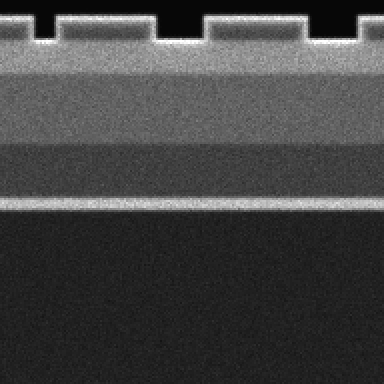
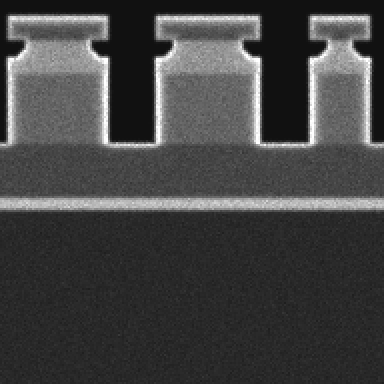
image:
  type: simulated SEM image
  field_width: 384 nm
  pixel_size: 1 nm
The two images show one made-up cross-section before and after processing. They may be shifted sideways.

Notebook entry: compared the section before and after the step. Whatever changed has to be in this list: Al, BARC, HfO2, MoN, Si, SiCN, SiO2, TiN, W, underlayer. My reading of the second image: SiO2 and W removed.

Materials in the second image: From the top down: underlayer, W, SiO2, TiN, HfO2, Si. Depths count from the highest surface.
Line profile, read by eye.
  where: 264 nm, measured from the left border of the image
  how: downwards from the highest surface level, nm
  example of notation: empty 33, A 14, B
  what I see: empty 128, TiN 54, HfO2 12, Si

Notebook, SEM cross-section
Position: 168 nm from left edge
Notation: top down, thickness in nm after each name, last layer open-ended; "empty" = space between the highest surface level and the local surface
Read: underlayer 24, empty 14, W 20, SiO2 70, TiN 54, HfO2 12, Si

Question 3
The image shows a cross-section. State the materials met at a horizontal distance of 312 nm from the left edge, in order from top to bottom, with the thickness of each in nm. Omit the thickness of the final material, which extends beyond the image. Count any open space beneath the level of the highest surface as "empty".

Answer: underlayer 24, empty 18, W 16, SiO2 70, TiN 54, HfO2 12, Si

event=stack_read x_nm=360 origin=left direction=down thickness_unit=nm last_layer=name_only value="underlayer 24, empty 18, W 16, SiO2 70, TiN 54, HfO2 12, Si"